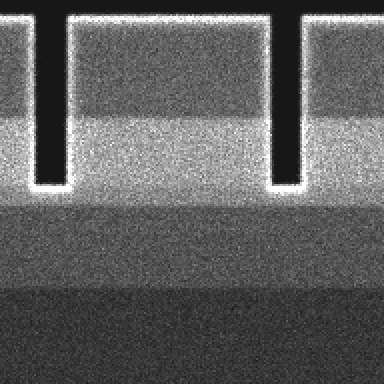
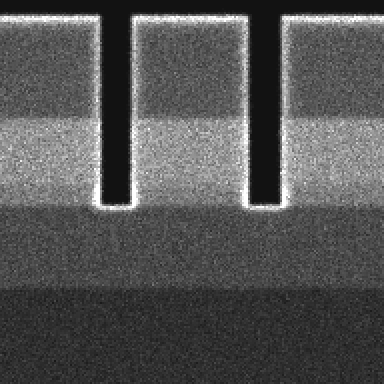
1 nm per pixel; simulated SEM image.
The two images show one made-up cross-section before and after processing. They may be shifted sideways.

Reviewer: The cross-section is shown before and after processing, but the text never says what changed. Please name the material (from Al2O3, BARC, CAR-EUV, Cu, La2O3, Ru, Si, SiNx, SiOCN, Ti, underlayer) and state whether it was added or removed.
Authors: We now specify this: Al2O3, removed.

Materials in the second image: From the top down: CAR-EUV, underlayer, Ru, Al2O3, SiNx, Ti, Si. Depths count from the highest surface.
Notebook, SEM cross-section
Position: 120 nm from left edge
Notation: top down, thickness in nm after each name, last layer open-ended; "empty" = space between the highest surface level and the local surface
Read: empty 190, SiNx 28, Ti 54, Si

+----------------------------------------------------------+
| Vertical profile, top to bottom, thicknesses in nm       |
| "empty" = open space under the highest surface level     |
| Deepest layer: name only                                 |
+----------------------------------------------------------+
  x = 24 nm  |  CAR-EUV 60, underlayer 42, Ru 68, Al2O3 20, SiNx 28, Ti 54, Si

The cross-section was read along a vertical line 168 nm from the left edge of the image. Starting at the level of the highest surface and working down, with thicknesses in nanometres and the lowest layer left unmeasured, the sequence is CAR-EUV 60, underlayer 42, Ru 68, Al2O3 20, SiNx 28, Ti 54, Si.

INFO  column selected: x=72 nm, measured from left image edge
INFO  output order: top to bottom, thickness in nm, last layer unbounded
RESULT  CAR-EUV 60, underlayer 42, Ru 68, Al2O3 20, SiNx 28, Ti 54, Si